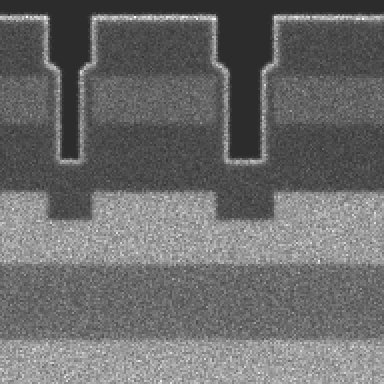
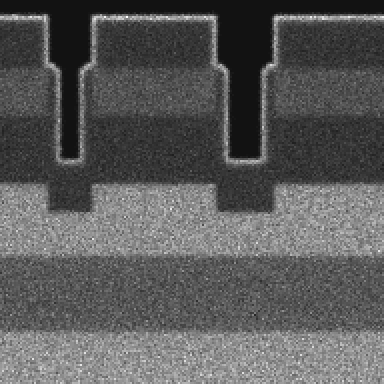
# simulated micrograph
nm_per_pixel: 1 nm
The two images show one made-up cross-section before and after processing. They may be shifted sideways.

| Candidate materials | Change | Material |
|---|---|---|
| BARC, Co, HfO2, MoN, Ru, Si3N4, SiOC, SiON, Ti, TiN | removed | Si3N4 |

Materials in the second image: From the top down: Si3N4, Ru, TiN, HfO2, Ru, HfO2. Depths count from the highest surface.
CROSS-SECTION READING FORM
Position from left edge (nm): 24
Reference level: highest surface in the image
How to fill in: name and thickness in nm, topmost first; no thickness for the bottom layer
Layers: Si3N4 52, Ru 48, TiN 68, HfO2 72, Ru 76, HfO2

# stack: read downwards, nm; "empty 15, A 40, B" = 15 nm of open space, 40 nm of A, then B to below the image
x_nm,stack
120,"Si3N4 52, Ru 48, TiN 68, HfO2 72, Ru 76, HfO2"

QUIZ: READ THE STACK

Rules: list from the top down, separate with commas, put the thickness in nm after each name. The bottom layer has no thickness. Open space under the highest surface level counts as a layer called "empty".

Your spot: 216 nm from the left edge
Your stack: empty 48, Si3N4 148, HfO2 44, Ru 76, HfO2